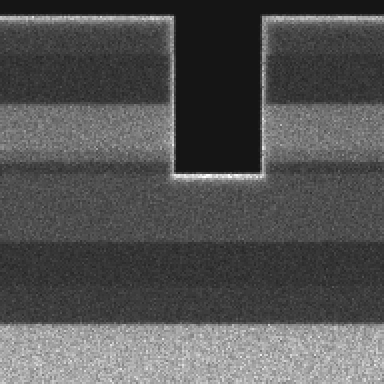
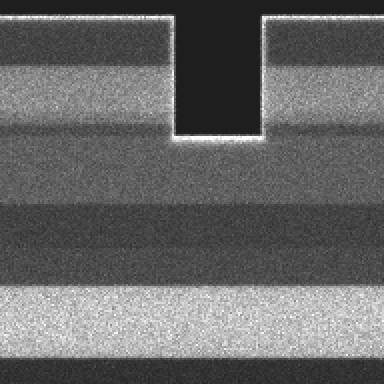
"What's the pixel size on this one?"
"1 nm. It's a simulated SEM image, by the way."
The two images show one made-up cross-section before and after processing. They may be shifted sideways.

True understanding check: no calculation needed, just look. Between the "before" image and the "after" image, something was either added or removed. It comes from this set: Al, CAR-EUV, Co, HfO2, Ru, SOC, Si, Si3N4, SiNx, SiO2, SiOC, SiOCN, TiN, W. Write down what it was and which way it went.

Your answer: SOC (removed)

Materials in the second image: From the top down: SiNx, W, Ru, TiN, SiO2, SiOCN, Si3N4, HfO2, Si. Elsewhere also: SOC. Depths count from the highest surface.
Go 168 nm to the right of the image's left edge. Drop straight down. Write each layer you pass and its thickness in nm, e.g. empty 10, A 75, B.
SiNx 50, W 46, Ru 12, TiN 12, SiO2 68, SiOCN 44, Si3N4 38, HfO2 72, Si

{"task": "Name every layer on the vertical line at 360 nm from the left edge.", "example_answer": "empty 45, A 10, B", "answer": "SiNx 50, W 46, Ru 12, TiN 12, SiO2 68, SiOCN 44, Si3N4 38, HfO2 72, Si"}